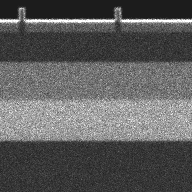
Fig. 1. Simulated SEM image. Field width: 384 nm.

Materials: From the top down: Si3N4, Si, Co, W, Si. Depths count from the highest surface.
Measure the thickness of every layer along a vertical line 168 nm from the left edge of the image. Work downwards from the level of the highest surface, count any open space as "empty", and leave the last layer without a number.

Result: empty 24, Si3N4 24, Si 60, Co 76, W 82, Si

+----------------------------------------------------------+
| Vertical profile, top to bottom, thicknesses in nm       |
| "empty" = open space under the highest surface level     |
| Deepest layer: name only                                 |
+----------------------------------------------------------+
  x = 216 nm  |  empty 24, Si3N4 24, Si 60, Co 76, W 82, Si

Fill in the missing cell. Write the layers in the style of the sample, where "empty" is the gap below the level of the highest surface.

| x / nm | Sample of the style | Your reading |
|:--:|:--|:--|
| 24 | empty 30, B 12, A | empty 24, Si3N4 24, Si 60, Co 76, W 82, Si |